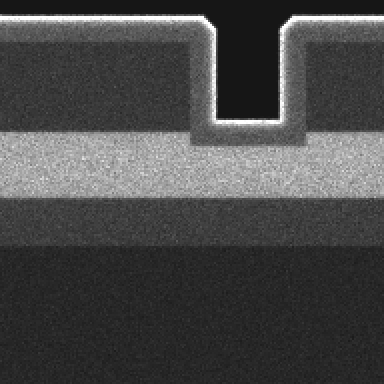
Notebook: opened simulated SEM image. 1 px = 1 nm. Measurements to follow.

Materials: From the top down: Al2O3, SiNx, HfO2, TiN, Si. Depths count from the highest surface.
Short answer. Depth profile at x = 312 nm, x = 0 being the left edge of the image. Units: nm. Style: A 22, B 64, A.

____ Al2O3 26, SiNx 90, HfO2 66, TiN 48, Si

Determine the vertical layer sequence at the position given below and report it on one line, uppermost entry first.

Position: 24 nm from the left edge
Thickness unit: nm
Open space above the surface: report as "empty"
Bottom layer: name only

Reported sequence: Al2O3 26, SiNx 90, HfO2 66, TiN 48, Si